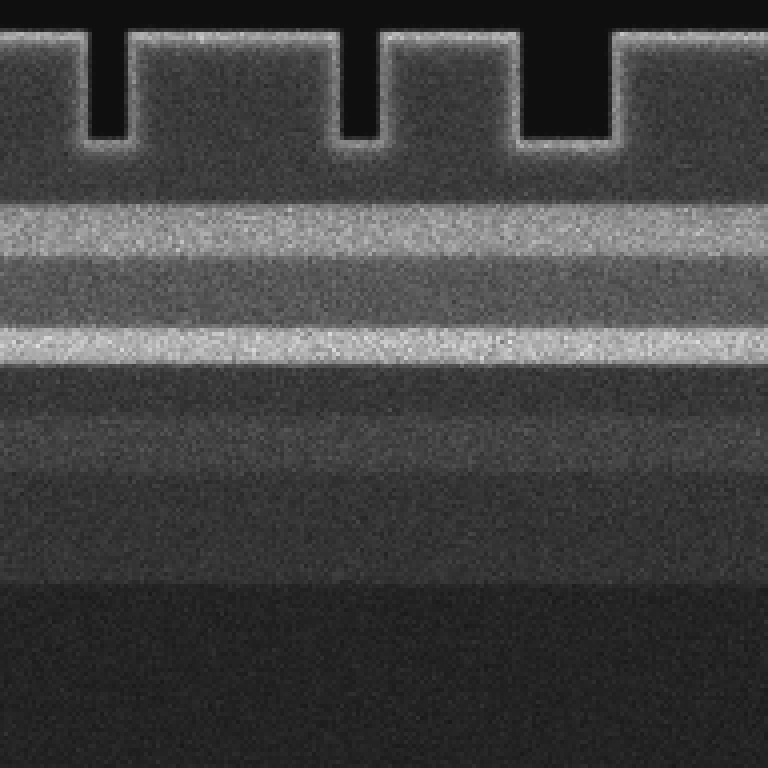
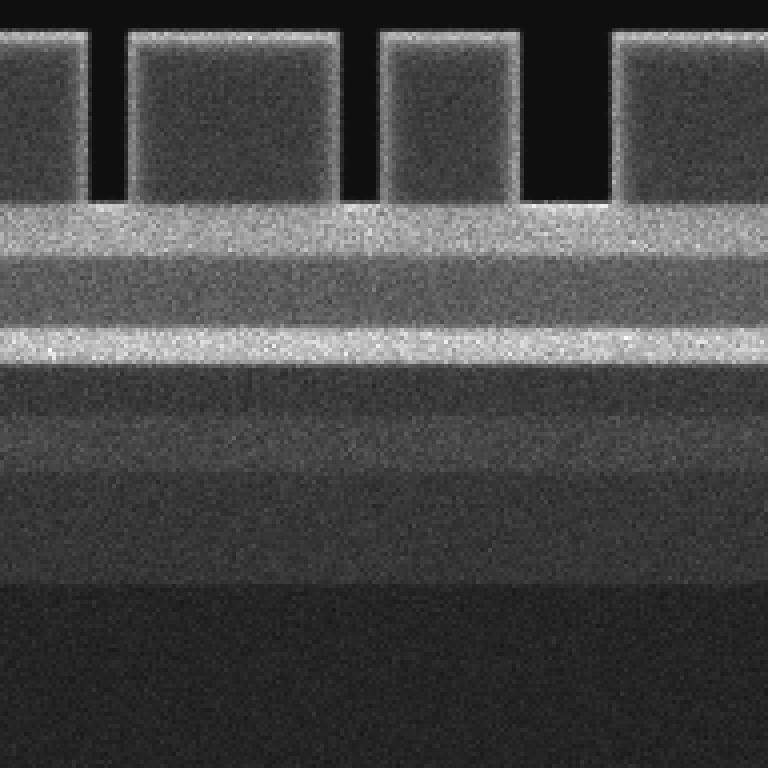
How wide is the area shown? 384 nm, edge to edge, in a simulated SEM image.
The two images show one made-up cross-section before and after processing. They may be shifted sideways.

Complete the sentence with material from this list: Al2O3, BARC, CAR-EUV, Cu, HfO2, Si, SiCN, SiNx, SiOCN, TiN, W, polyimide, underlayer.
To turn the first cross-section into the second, underlayer must be removed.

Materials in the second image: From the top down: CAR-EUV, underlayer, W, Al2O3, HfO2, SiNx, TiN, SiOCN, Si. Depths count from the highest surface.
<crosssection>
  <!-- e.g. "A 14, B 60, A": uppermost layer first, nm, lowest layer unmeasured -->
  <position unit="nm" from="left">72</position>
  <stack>CAR-EUV 54, underlayer 32, W 26, Al2O3 36, HfO2 18, SiNx 26, TiN 28, SiOCN 56, Si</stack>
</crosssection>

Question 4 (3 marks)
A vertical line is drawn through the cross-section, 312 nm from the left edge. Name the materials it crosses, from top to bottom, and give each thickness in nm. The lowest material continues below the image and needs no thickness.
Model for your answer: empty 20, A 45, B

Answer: CAR-EUV 54, underlayer 32, W 26, Al2O3 36, HfO2 18, SiNx 26, TiN 28, SiOCN 56, Si